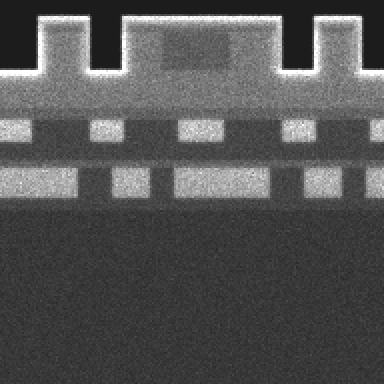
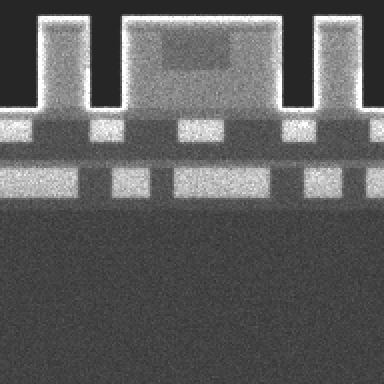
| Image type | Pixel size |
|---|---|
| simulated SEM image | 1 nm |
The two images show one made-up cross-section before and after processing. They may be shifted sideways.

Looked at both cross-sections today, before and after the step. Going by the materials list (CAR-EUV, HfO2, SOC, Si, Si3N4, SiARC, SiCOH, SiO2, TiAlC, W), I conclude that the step removed SiO2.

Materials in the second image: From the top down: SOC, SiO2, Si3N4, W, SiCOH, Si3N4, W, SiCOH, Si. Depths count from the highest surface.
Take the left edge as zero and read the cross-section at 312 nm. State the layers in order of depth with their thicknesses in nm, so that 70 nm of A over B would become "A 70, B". empty 92, Si3N4 12, W 22, SiCOH 18, Si3N4 8, W 30, SiCOH 12, Si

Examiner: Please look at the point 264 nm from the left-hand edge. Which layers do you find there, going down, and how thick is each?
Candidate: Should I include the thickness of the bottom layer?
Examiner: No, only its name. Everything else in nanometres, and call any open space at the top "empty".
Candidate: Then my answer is SOC 16, SiO2 76, Si3N4 12, SiCOH 40, Si3N4 8, W 30, SiCOH 12, Si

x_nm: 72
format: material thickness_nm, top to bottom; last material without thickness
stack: SOC 16, SiO2 76, Si3N4 12, SiCOH 40, Si3N4 8, W 30, SiCOH 12, Si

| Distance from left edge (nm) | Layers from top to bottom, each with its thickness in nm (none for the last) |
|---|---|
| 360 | SOC 54, SiO2 38, Si3N4 12, SiCOH 40, Si3N4 8, SiCOH 42, Si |